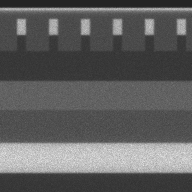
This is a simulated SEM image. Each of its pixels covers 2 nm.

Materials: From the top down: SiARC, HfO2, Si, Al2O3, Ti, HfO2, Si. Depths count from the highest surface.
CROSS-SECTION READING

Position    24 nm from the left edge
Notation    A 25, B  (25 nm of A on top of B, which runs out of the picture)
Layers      SiARC 86, Si 60, Al2O3 58, Ti 66, HfO2 60, Si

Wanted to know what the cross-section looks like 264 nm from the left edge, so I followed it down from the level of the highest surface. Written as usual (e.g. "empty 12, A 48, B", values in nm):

SiARC 86, Si 60, Al2O3 58, Ti 66, HfO2 60, Si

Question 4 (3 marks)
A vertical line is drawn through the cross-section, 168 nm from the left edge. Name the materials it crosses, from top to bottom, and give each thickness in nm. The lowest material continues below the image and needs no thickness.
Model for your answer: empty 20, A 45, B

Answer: SiARC 22, HfO2 32, Si 92, Al2O3 58, Ti 66, HfO2 60, Si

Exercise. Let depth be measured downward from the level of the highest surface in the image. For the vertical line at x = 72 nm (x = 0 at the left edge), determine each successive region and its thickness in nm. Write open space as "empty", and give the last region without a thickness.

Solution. SiARC 86, Si 60, Al2O3 58, Ti 66, HfO2 60, Si